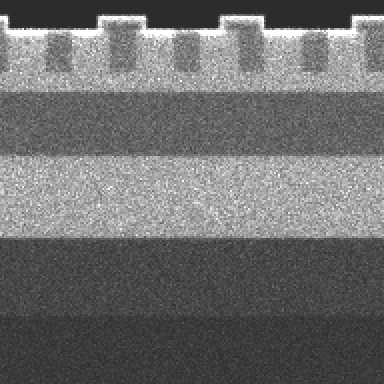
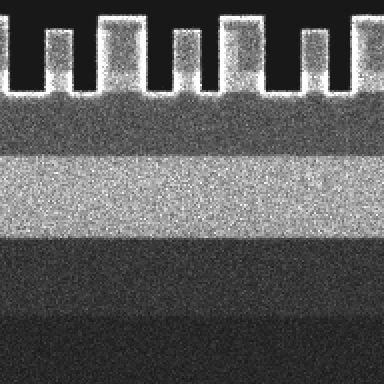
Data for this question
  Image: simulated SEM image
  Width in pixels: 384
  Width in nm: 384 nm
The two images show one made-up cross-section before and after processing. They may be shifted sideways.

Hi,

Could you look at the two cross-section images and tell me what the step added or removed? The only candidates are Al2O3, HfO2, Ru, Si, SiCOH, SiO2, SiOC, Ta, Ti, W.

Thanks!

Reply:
removed HfO2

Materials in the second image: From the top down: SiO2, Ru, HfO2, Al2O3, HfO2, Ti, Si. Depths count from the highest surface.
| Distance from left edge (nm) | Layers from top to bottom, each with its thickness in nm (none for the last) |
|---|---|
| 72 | empty 76, Al2O3 64, HfO2 82, Ti 78, Si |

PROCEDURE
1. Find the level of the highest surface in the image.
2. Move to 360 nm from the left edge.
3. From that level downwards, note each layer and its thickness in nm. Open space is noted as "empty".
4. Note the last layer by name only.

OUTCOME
SiO2 14, HfO2 62, Al2O3 64, HfO2 82, Ti 78, Si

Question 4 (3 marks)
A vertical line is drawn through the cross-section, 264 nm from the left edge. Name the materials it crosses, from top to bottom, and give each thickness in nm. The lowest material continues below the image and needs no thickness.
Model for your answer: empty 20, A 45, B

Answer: empty 76, Al2O3 64, HfO2 82, Ti 78, Si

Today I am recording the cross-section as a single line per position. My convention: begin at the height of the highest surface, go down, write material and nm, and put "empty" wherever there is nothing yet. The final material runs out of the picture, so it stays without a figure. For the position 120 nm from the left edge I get SiO2 14, Ru 42, HfO2 20, Al2O3 64, HfO2 82, Ti 78, Si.